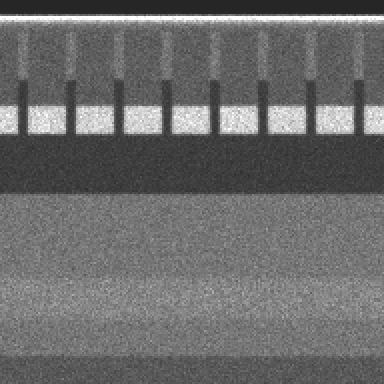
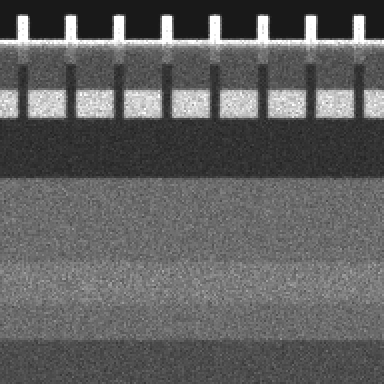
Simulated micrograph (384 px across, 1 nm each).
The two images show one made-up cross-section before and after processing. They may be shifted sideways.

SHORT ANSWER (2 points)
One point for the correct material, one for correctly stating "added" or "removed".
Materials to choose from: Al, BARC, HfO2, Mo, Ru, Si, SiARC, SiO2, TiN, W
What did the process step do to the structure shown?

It removed SiARC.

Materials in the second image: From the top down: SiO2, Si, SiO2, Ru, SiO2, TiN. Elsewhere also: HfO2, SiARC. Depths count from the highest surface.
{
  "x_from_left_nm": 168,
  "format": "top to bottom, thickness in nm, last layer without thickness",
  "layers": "SiO2 48, Si 114, SiO2 84, Ru 42, SiO2 36, TiN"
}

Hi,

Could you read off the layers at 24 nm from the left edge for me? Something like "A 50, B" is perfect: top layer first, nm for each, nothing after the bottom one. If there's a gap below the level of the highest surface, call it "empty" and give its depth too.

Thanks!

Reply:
SiO2 48, Si 114, SiO2 84, Ru 42, SiO2 36, TiN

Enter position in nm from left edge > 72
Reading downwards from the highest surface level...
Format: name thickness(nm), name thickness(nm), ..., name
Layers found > SiO2 48, Si 114, SiO2 84, Ru 42, SiO2 36, TiN